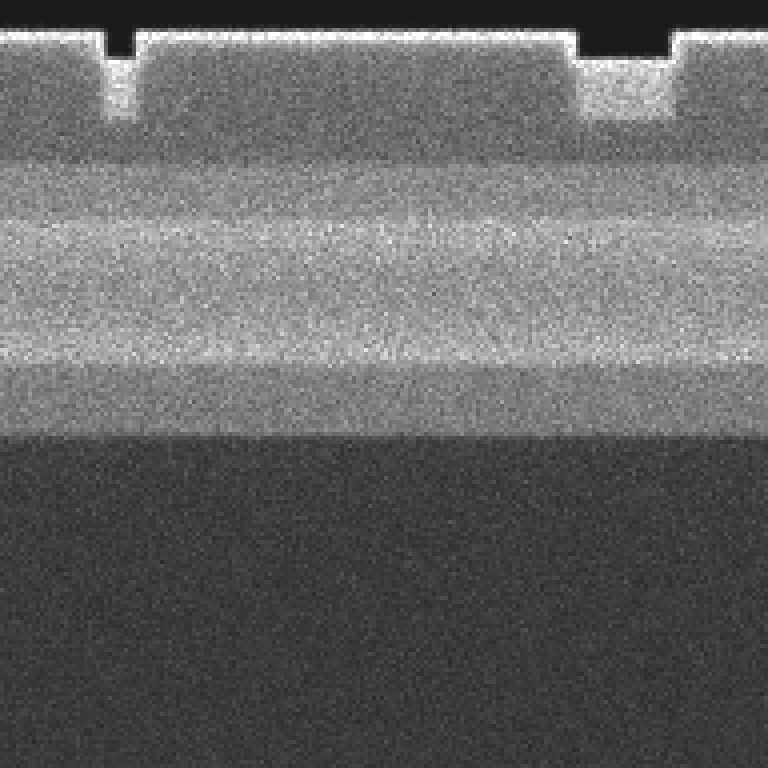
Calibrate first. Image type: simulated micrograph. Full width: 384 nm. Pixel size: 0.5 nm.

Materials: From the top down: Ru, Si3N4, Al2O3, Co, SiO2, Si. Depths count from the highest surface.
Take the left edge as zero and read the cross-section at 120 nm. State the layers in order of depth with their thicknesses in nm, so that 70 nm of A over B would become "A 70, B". Si3N4 66, Al2O3 28, Co 72, SiO2 36, Si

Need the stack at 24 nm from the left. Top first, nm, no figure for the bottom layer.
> Si3N4 66, Al2O3 28, Co 72, SiO2 36, Si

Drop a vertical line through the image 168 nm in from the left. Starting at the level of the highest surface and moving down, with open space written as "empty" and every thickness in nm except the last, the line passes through Si3N4 66, Al2O3 28, Co 72, SiO2 36, Si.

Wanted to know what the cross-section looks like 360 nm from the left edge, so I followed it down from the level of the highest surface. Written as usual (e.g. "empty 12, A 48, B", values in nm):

Si3N4 66, Al2O3 28, Co 72, SiO2 36, Si